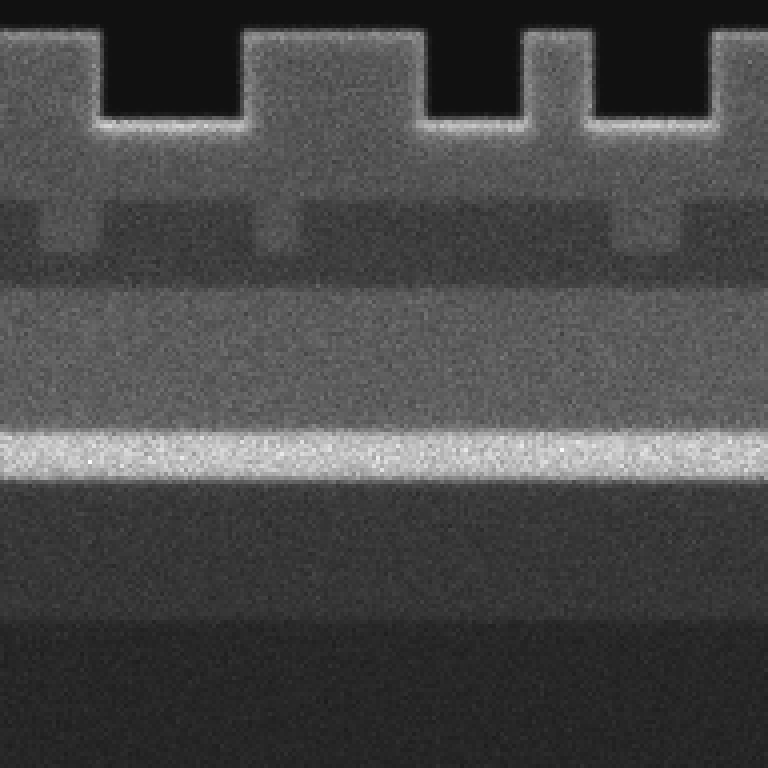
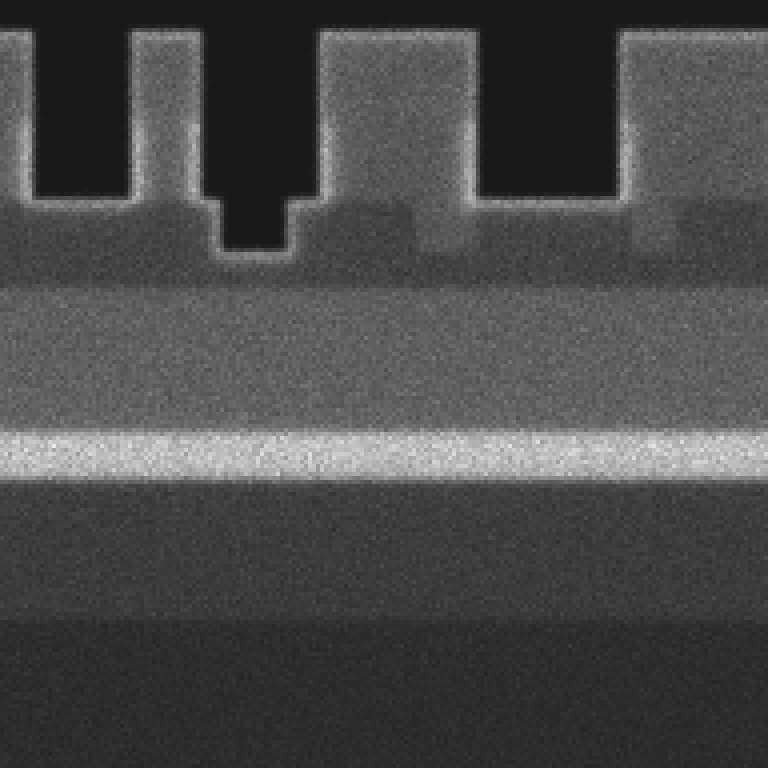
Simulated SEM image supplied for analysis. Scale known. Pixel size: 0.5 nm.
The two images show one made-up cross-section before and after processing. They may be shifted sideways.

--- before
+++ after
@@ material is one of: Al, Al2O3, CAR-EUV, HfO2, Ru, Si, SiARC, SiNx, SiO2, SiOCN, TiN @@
SiO2 removed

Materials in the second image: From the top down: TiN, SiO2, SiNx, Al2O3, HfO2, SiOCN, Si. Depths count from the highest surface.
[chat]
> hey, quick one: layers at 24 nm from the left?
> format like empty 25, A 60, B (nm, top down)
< empty 84, SiNx 44, Al2O3 72, HfO2 24, SiOCN 70, Si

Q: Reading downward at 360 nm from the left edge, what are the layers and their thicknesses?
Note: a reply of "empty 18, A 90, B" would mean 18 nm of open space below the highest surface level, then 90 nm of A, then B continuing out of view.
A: TiN 44, SiO2 40, SiNx 44, Al2O3 72, HfO2 24, SiOCN 70, Si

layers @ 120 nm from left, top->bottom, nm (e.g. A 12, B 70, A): empty 110, SiNx 18, Al2O3 72, HfO2 24, SiOCN 70, Si